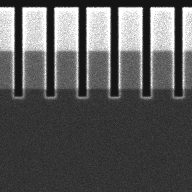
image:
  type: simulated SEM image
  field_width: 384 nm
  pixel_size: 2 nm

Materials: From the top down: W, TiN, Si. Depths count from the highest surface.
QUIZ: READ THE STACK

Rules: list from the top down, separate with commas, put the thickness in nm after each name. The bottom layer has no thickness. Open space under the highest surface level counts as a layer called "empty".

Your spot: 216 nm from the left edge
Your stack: W 86, TiN 76, Si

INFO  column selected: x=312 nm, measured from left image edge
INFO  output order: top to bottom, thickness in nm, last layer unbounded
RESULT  W 86, TiN 76, Si